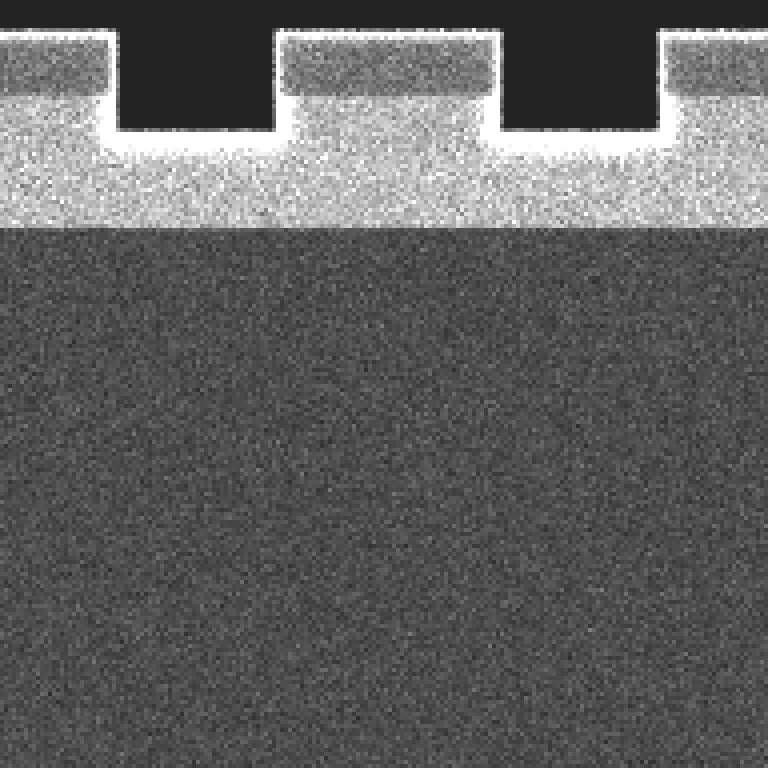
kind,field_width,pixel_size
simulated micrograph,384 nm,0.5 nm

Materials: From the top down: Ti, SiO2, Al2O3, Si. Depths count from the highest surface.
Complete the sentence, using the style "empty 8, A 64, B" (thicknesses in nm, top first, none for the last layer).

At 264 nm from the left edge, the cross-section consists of empty 50, SiO2 10, Al2O3 38, Si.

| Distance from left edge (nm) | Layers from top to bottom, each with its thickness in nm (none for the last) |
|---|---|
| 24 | Ti 32, SiO2 28, Al2O3 38, Si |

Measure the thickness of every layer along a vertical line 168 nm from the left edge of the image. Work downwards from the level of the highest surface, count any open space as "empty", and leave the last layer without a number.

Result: Ti 32, SiO2 28, Al2O3 38, Si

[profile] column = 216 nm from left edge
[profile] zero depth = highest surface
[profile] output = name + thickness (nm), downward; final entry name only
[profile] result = Ti 32, SiO2 28, Al2O3 38, Si